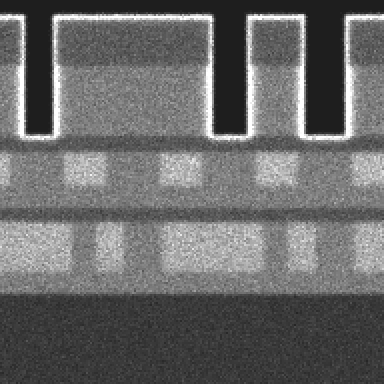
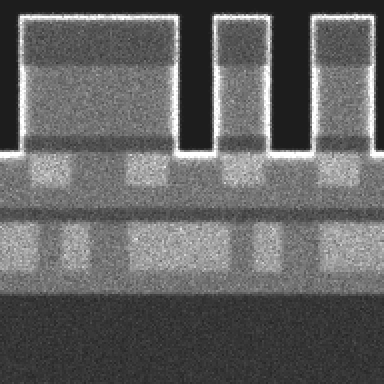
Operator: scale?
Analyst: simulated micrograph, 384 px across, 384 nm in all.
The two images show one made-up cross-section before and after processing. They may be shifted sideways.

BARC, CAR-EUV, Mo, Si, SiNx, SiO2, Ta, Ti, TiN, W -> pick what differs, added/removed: SiNx removed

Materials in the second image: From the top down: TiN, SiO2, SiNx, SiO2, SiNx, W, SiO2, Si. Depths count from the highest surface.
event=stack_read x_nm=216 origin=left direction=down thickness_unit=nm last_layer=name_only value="TiN 50, SiO2 70, SiNx 16, SiO2 56, SiNx 14, W 50, SiO2 22, Si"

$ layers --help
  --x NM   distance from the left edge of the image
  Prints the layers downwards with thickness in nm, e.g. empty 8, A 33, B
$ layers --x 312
TiN 50, SiO2 70, SiNx 16, SiO2 56, SiNx 14, SiO2 72, Si